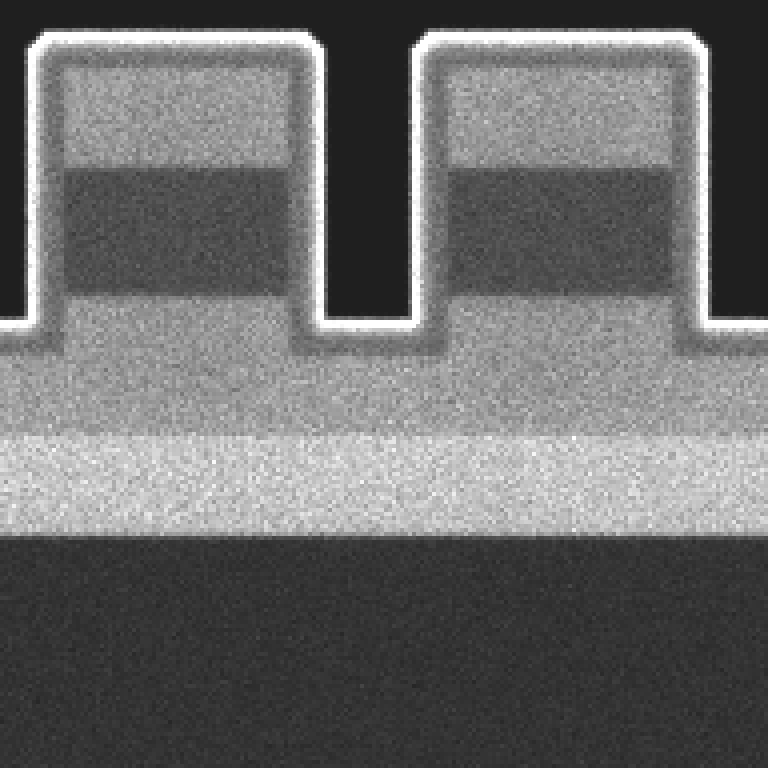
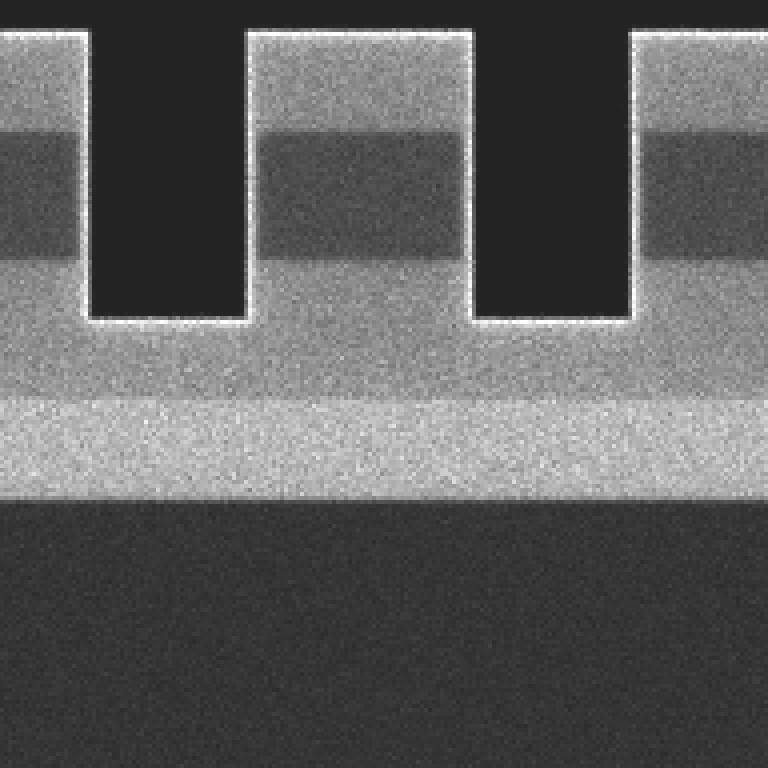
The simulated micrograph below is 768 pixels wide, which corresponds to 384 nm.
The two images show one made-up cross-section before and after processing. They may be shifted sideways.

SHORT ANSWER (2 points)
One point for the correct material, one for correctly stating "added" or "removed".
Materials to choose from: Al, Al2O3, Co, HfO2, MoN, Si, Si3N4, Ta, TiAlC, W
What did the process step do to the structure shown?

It removed Al2O3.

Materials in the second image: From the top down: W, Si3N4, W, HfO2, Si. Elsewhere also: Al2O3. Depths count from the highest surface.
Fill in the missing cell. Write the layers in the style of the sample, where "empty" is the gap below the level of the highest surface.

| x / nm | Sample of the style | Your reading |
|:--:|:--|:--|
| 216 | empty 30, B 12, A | W 50, Si3N4 64, W 70, HfO2 50, Si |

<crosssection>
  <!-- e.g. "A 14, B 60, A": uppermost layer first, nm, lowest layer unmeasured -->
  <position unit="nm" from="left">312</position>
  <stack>empty 144, W 40, HfO2 50, Si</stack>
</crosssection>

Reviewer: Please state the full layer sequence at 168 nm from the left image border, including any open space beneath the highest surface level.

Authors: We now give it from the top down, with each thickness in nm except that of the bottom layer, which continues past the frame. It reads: W 50, Si3N4 64, W 70, HfO2 50, Si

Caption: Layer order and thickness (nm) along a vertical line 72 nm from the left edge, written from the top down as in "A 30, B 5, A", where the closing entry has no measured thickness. empty 144, W 40, HfO2 50, Si